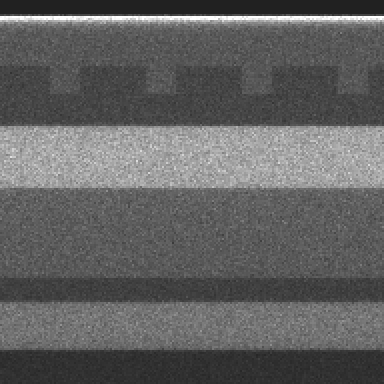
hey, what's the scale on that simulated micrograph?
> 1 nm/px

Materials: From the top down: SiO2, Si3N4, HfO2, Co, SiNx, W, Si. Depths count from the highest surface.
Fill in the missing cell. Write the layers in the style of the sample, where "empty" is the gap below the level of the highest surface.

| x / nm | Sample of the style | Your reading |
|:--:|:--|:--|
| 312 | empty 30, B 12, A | SiO2 50, Si3N4 60, HfO2 62, Co 90, SiNx 24, W 48, Si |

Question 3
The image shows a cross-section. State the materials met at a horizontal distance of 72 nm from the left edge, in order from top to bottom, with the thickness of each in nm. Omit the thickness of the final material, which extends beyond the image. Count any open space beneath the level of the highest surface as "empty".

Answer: SiO2 78, Si3N4 32, HfO2 62, Co 90, SiNx 24, W 48, Si